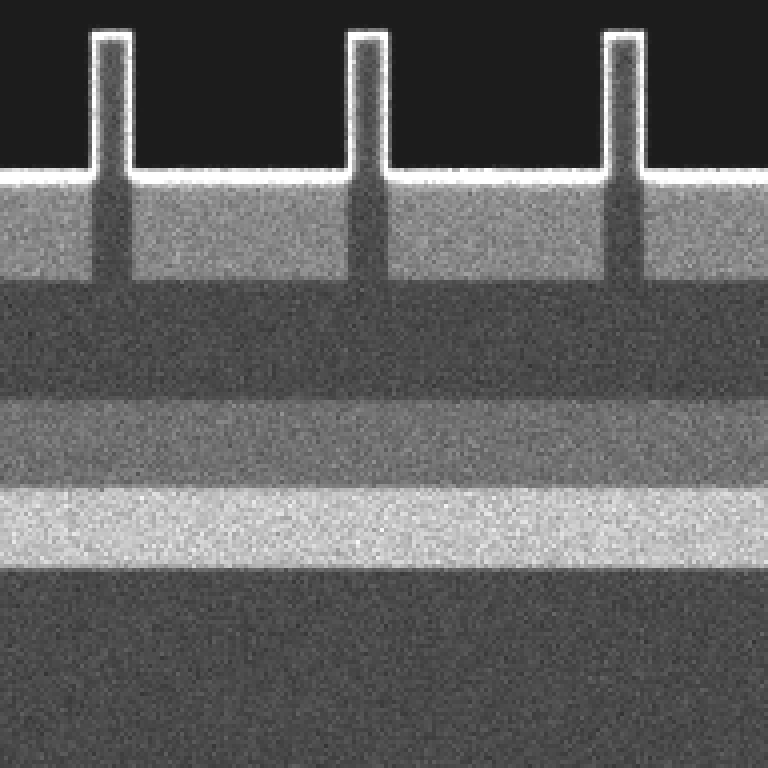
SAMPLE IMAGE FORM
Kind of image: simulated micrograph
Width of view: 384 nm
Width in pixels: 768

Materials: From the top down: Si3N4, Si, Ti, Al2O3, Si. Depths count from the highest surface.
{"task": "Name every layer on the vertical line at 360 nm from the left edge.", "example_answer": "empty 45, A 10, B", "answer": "empty 70, Si3N4 54, Si 60, Ti 44, Al2O3 40, Si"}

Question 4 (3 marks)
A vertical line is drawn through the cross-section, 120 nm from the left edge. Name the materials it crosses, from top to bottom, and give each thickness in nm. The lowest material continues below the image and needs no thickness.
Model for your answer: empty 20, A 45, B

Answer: empty 70, Si3N4 54, Si 60, Ti 44, Al2O3 40, Si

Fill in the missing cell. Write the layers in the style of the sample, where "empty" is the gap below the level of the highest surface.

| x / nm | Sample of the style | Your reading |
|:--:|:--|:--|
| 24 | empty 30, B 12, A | empty 70, Si3N4 54, Si 60, Ti 44, Al2O3 40, Si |